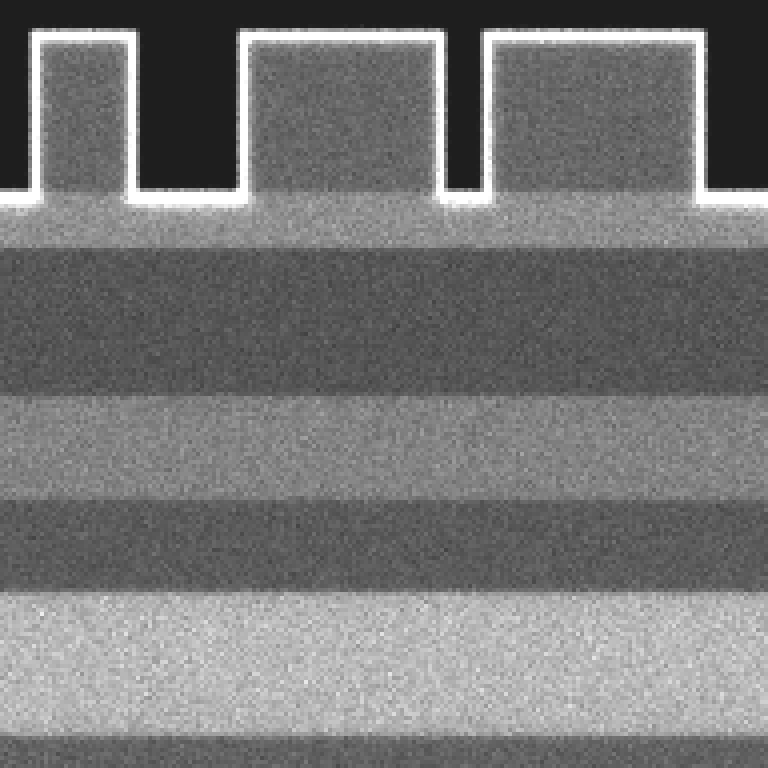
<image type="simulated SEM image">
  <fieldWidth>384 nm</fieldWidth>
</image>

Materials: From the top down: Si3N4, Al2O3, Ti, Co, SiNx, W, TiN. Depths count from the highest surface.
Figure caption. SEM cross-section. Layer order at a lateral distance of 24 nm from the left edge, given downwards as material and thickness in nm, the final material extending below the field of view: Si3N4 80, Al2O3 28, Ti 74, Co 52, SiNx 46, W 72, TiN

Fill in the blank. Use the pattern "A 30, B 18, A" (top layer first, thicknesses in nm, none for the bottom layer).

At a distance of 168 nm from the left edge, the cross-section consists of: Si3N4 80, Al2O3 28, Ti 74, Co 52, SiNx 46, W 72, TiN